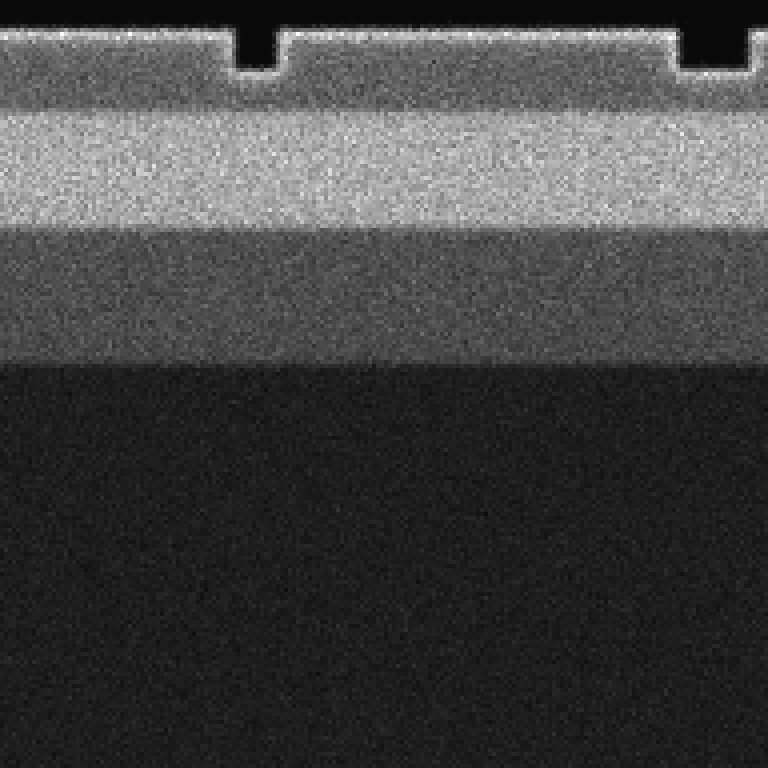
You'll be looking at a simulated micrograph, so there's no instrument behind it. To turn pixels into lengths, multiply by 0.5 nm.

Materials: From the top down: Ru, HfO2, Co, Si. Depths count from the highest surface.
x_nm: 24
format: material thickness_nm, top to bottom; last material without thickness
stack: Ru 40, HfO2 58, Co 68, Si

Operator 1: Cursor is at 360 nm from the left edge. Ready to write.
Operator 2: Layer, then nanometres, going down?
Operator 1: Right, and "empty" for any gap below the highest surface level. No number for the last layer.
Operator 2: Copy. empty 20, Ru 20, HfO2 58, Co 68, Si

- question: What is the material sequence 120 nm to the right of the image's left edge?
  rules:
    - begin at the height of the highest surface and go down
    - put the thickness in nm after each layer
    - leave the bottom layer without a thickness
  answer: empty 20, Ru 20, HfO2 58, Co 68, Si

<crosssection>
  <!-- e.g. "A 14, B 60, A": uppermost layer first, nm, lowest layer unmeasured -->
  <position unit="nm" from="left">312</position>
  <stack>Ru 40, HfO2 58, Co 68, Si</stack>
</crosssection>